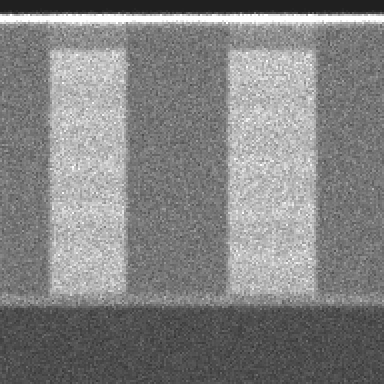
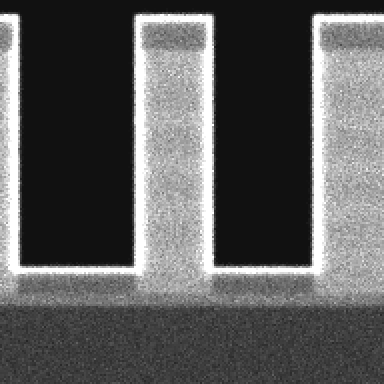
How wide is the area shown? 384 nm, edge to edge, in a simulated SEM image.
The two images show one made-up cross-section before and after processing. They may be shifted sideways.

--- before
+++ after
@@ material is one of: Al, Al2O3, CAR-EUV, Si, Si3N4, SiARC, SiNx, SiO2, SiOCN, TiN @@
SiOCN removed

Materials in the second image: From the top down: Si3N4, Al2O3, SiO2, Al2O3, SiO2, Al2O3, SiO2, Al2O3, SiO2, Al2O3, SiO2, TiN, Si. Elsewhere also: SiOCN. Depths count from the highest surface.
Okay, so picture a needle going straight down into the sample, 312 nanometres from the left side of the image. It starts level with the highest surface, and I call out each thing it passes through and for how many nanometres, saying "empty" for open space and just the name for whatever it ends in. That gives empty 252, SiOCN 26, TiN 12, Si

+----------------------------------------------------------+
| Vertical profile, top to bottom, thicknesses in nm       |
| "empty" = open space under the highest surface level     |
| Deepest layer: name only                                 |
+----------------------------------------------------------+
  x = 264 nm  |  empty 252, SiOCN 26, TiN 12, Si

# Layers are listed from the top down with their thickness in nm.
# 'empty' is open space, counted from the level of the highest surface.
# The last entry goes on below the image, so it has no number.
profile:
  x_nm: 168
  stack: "Si3N4 34, Al2O3 32, SiO2 28, Al2O3 18, SiO2 28, Al2O3 18, SiO2 28, Al2O3 18, SiO2 28, Al2O3 18, SiO2 28, TiN 12, Si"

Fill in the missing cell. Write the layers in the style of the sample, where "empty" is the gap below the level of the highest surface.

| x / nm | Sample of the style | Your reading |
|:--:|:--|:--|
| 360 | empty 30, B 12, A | Si3N4 34, Al2O3 32, SiO2 28, Al2O3 18, SiO2 28, Al2O3 18, SiO2 28, Al2O3 18, SiO2 28, Al2O3 18, SiO2 28, TiN 12, Si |